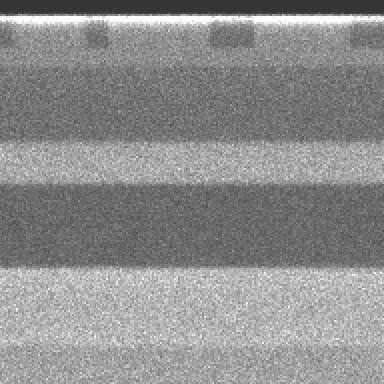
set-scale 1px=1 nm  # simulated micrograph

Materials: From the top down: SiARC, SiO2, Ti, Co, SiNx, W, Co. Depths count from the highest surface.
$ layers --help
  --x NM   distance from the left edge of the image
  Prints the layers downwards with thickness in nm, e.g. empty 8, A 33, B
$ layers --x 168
SiO2 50, Ti 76, Co 42, SiNx 84, W 78, Co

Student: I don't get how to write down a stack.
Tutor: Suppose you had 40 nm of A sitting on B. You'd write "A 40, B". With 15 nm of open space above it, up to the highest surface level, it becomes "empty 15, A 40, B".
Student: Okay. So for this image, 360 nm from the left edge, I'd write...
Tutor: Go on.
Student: SiARC 32, SiO2 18, Ti 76, Co 42, SiNx 84, W 78, Co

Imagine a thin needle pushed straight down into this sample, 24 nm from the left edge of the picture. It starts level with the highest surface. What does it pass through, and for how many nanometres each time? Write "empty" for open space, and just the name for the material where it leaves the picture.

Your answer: SiO2 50, Ti 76, Co 42, SiNx 84, W 78, Co